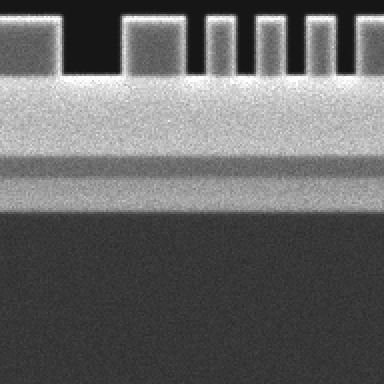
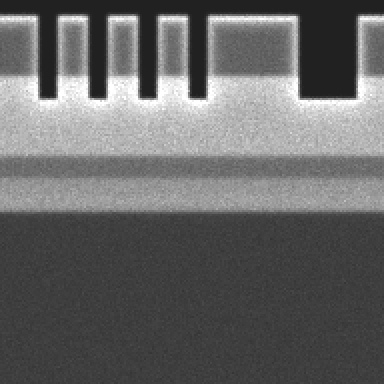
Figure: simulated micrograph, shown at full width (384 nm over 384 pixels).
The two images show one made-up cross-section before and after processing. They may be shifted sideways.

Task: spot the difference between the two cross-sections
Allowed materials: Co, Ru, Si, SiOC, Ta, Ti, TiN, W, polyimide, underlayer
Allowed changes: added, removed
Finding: removed W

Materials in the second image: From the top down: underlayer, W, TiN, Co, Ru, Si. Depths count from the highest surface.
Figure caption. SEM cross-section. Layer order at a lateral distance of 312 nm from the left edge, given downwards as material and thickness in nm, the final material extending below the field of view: empty 84, W 56, TiN 22, Co 18, Ru 16, Si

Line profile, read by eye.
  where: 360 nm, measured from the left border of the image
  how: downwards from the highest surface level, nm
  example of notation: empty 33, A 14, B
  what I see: underlayer 60, W 80, TiN 22, Co 18, Ru 16, Si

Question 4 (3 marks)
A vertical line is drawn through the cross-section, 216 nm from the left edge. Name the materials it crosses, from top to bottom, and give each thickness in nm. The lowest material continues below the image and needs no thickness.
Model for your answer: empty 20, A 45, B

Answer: underlayer 60, W 80, TiN 22, Co 18, Ru 16, Si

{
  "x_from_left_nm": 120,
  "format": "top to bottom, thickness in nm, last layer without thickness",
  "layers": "underlayer 60, W 80, TiN 22, Co 18, Ru 16, Si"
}